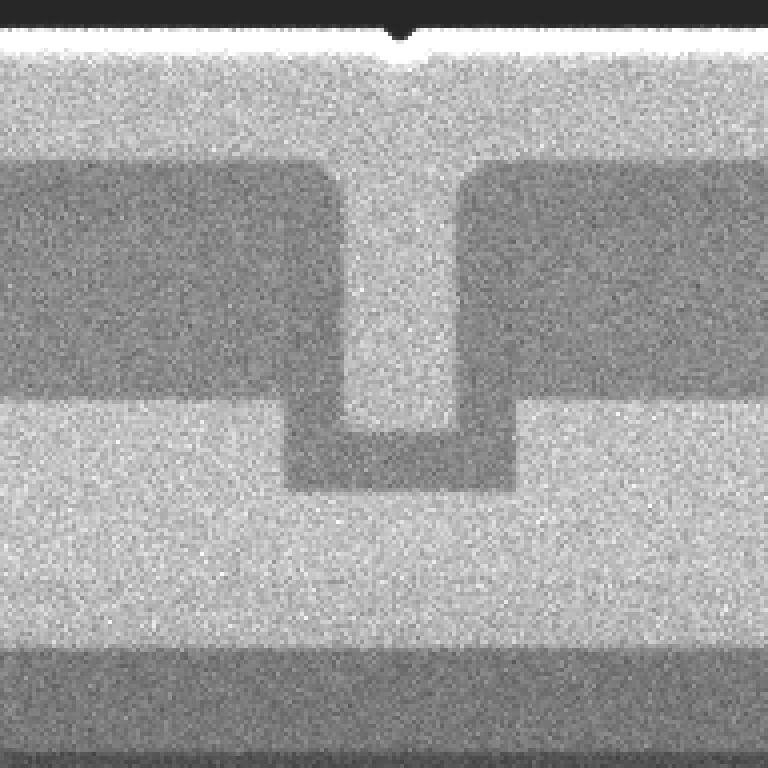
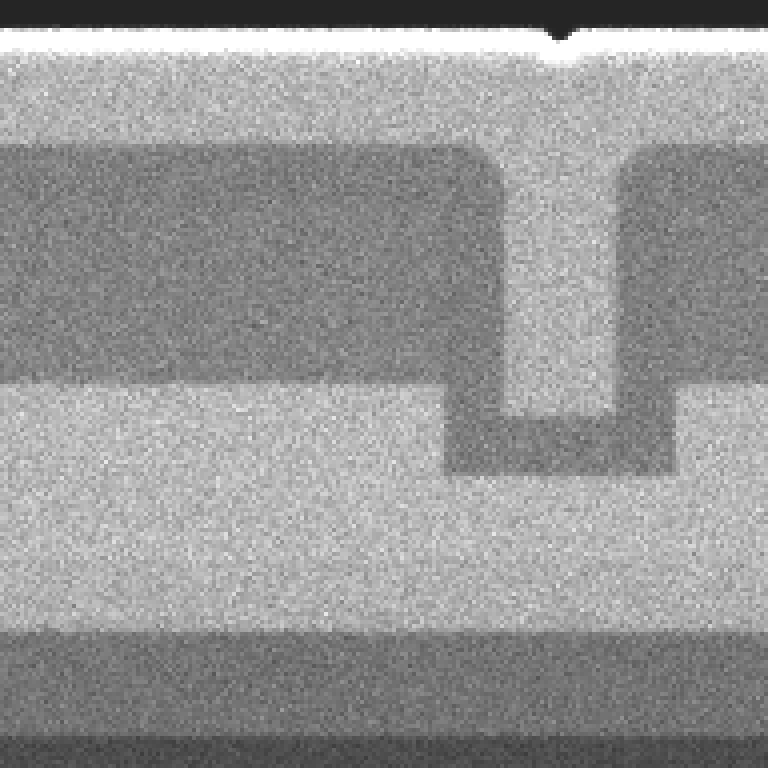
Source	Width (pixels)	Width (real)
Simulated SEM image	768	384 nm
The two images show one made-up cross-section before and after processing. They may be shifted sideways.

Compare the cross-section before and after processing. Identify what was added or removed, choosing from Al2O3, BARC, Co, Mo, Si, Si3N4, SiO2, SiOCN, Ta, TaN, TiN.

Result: SiO2 removed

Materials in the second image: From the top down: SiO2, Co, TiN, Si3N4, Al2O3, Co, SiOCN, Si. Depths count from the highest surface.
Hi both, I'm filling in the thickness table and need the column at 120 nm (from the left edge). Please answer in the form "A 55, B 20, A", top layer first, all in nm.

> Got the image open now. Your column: SiO2 46, Co 10, TiN 30, Si3N4 90, Al2O3 88, Co 36, SiOCN 52, Si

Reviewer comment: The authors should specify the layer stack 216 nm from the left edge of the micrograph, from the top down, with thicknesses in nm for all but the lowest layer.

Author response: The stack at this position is SiO2 46, Co 10, TiN 30, Si3N4 90, Al2O3 88, Co 36, SiOCN 52, Si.